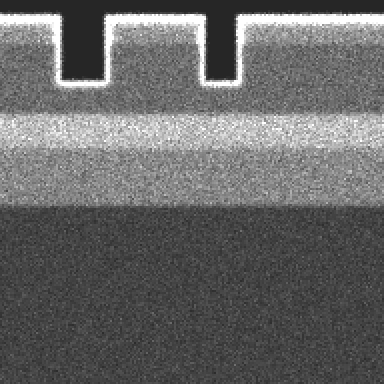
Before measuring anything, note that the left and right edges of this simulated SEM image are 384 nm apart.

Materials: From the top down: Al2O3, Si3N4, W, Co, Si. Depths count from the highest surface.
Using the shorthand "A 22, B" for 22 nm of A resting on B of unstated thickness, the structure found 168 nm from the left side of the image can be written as Al2O3 28, Si3N4 70, W 34, Co 58, Si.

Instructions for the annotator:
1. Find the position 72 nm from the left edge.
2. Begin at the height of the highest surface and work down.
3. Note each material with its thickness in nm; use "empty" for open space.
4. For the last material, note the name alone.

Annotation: empty 66, Si3N4 32, W 34, Co 58, Si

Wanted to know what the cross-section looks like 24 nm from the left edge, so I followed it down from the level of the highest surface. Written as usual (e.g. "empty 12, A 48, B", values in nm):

Al2O3 28, Si3N4 70, W 34, Co 58, Si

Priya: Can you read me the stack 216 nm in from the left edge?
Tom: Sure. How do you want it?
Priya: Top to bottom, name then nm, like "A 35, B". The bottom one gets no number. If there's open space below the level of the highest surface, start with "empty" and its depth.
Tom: empty 66, Si3N4 32, W 34, Co 58, Si